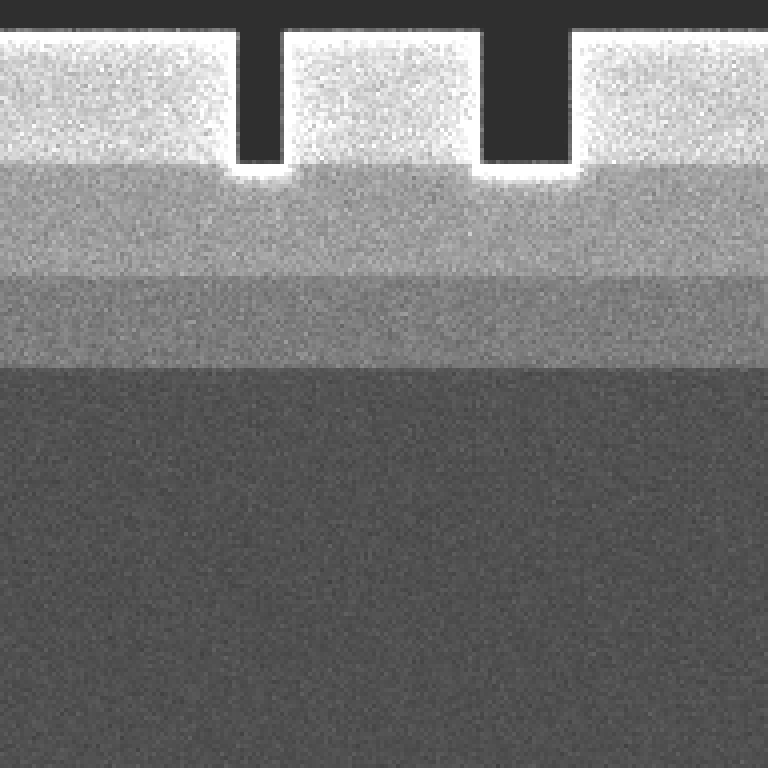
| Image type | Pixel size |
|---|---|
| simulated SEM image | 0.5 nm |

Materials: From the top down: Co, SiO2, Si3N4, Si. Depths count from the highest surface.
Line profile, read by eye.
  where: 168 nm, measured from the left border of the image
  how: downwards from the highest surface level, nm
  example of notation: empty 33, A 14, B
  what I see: Co 66, SiO2 56, Si3N4 46, Si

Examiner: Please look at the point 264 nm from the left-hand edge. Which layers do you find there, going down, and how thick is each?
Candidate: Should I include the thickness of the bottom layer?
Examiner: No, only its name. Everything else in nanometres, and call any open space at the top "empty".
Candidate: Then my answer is empty 66, SiO2 56, Si3N4 46, Si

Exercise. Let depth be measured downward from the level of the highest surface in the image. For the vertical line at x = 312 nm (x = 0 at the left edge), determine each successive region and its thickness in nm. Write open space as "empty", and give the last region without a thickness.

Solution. Co 66, SiO2 56, Si3N4 46, Si